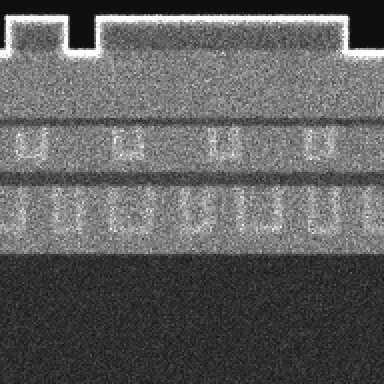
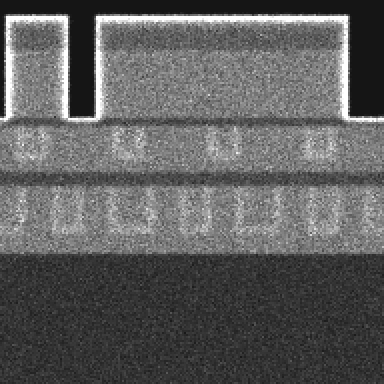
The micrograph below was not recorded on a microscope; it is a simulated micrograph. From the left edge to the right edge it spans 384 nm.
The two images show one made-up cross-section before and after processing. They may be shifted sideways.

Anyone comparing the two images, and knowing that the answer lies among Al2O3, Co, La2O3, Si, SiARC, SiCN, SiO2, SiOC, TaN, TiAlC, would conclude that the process removed SiO2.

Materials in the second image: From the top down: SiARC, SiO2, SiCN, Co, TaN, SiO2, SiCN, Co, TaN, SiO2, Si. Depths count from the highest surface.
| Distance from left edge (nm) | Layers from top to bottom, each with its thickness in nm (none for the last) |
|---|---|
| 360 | empty 102, SiCN 8, SiO2 46, SiCN 14, SiO2 68, Si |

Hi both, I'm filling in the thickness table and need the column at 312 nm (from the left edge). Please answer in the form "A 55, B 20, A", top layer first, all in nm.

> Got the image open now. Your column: SiARC 34, SiO2 68, SiCN 8, Co 26, TaN 8, SiO2 12, SiCN 14, TaN 48, SiO2 20, Si